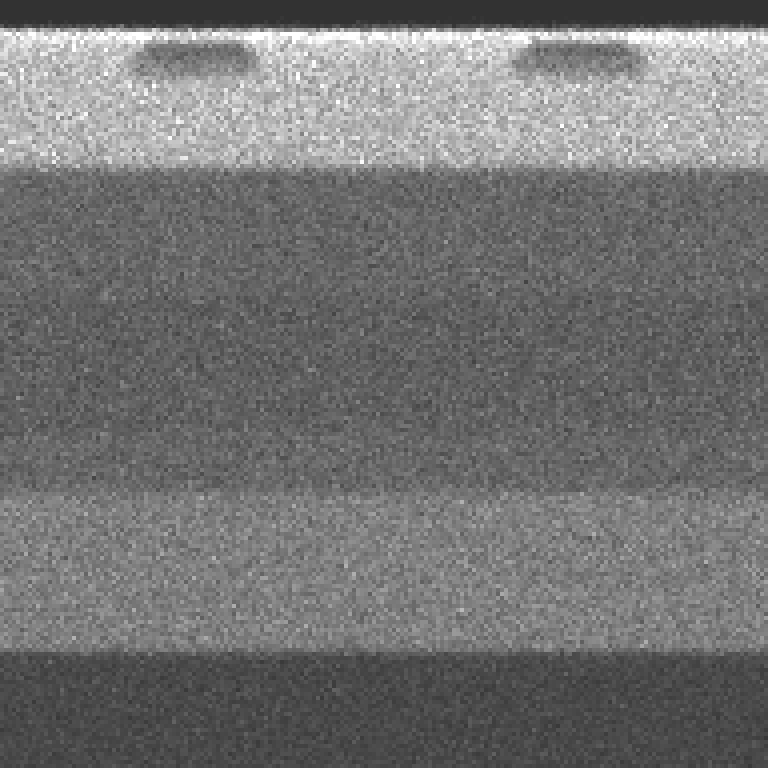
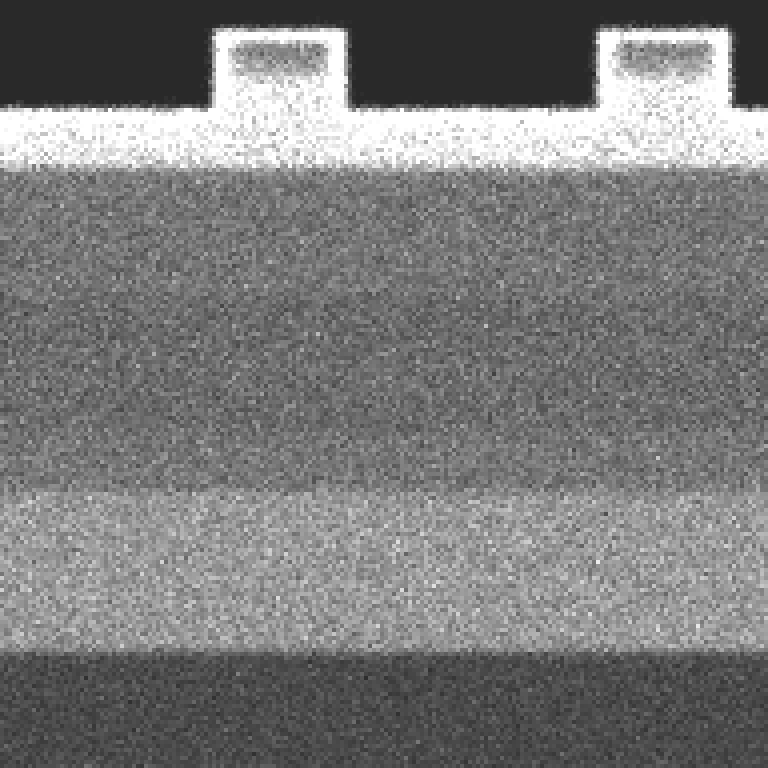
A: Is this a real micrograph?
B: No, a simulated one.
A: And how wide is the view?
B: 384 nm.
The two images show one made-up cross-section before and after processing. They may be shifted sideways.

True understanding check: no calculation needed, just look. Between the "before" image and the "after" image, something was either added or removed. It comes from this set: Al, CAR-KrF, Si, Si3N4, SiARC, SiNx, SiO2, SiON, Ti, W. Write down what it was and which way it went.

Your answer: W (removed)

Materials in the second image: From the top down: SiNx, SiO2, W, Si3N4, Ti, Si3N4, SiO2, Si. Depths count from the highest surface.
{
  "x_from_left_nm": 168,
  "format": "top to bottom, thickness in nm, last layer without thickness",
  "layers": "SiO2 22, W 46, Si3N4 64, Ti 68, Si3N4 30, SiO2 80, Si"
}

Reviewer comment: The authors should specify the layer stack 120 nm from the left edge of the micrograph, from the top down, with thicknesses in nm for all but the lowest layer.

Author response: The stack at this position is SiNx 12, SiO2 10, W 46, Si3N4 64, Ti 68, Si3N4 30, SiO2 80, Si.